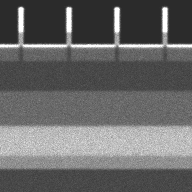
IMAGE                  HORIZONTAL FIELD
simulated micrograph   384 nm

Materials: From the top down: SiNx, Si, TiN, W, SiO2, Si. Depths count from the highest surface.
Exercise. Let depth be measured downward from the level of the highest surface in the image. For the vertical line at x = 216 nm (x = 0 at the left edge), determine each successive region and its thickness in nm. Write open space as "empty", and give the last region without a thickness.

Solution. empty 74, SiNx 32, Si 60, TiN 70, W 60, SiO2 26, Si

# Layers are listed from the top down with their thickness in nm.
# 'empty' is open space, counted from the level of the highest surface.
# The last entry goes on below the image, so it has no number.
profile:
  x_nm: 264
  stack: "empty 74, SiNx 32, Si 60, TiN 70, W 60, SiO2 26, Si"